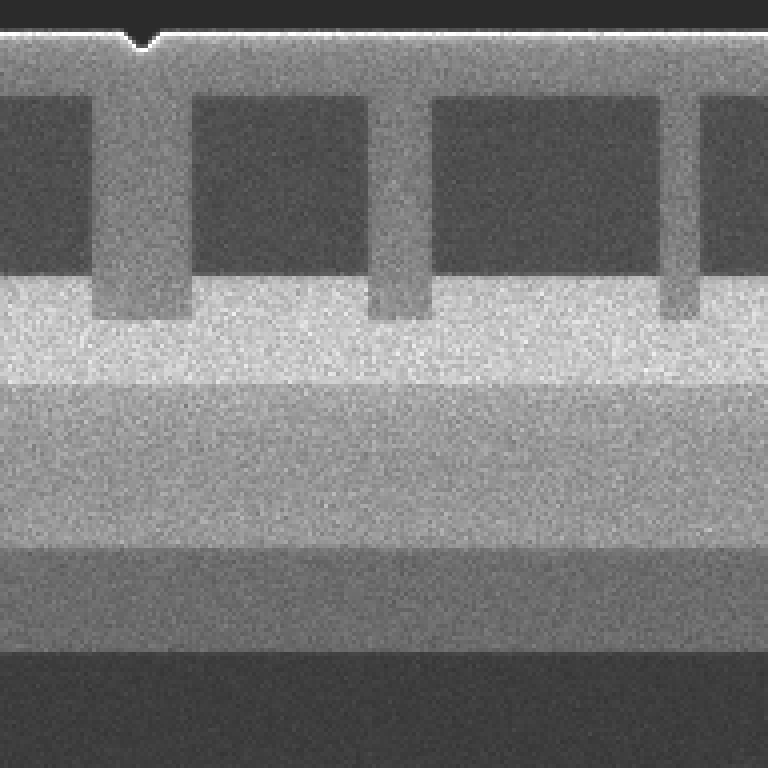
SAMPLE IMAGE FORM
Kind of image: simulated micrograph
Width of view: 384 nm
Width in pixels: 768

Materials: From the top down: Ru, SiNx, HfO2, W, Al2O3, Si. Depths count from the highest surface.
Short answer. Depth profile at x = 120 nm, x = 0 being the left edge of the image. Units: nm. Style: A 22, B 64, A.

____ Ru 32, SiNx 90, HfO2 54, W 82, Al2O3 52, Si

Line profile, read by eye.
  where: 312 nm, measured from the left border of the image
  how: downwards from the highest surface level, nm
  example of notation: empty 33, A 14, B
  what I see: Ru 32, SiNx 90, HfO2 54, W 82, Al2O3 52, Si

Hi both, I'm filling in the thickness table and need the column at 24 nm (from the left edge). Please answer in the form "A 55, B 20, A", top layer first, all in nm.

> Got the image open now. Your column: Ru 32, SiNx 90, HfO2 54, W 82, Al2O3 52, Si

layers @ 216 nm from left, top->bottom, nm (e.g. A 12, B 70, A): Ru 32, SiNx 90, HfO2 54, W 82, Al2O3 52, Si